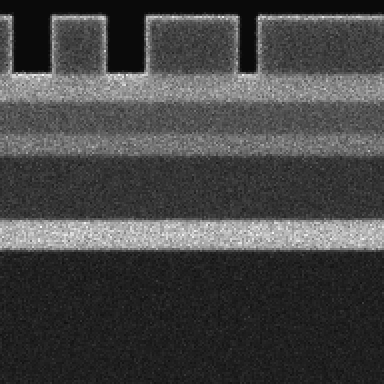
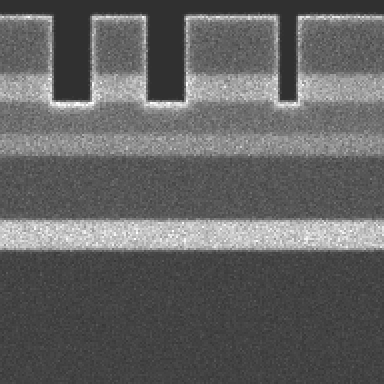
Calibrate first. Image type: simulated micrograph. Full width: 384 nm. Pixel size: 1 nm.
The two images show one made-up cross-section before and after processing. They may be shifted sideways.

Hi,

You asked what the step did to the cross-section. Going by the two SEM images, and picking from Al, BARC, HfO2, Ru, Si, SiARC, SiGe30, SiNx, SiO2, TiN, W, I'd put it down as W, removed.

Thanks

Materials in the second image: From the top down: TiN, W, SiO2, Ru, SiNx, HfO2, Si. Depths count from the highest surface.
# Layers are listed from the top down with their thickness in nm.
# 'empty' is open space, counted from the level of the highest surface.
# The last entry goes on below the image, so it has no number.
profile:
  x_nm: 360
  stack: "TiN 58, W 28, SiO2 32, Ru 22, SiNx 64, HfO2 30, Si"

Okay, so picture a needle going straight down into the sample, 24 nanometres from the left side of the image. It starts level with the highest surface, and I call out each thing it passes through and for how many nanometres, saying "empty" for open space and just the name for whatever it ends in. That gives TiN 58, W 28, SiO2 32, Ru 22, SiNx 64, HfO2 30, Si